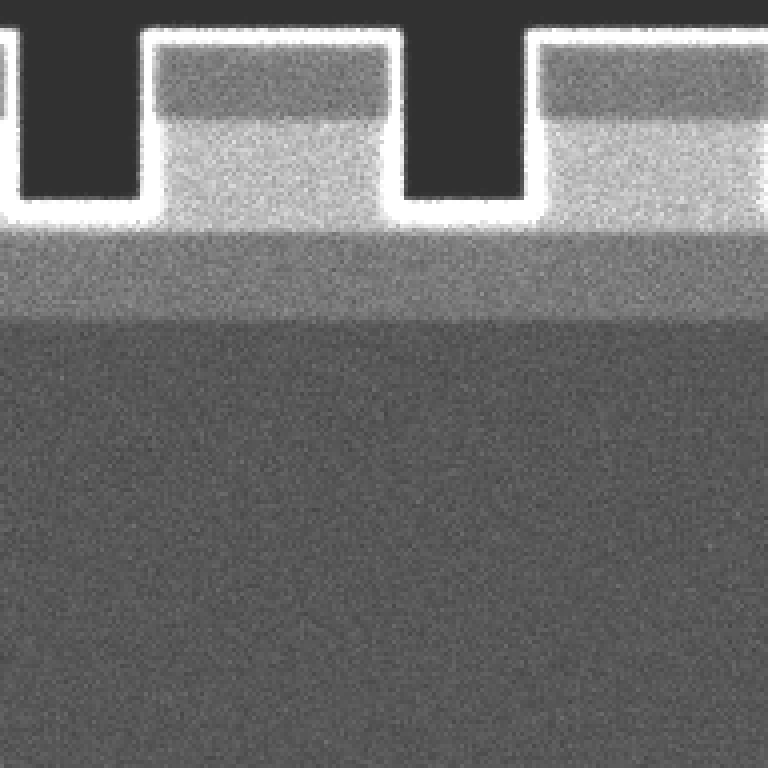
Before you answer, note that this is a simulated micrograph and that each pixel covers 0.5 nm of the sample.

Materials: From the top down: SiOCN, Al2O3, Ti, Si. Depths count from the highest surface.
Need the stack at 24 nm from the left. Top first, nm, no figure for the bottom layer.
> empty 86, Al2O3 14, Ti 44, Si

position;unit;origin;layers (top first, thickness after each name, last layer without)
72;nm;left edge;SiOCN 44, Al2O3 56, Ti 44, Si